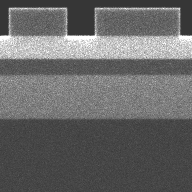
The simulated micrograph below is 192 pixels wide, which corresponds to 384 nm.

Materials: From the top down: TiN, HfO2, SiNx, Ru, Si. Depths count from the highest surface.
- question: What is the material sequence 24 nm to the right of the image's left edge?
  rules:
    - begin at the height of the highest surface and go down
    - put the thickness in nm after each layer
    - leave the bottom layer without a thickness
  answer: TiN 56, HfO2 46, SiNx 32, Ru 88, Si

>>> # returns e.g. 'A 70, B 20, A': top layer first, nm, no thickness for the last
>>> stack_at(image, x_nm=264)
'TiN 56, HfO2 46, SiNx 32, Ru 88, Si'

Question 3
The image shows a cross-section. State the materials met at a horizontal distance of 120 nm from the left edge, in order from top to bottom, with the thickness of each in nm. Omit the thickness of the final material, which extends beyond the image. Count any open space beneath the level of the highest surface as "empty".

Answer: TiN 56, HfO2 46, SiNx 32, Ru 88, Si